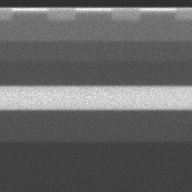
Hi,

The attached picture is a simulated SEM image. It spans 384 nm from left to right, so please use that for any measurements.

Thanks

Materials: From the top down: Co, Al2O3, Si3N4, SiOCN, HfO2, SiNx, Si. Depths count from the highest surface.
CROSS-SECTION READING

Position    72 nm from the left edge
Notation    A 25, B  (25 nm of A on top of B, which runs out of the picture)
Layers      Al2O3 66, Si3N4 40, SiOCN 50, HfO2 48, SiNx 64, Si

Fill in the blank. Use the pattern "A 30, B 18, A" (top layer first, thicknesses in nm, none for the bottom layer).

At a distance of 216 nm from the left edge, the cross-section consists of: Al2O3 66, Si3N4 40, SiOCN 50, HfO2 48, SiNx 64, Si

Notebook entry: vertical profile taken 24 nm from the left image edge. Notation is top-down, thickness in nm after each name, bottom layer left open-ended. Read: Al2O3 66, Si3N4 40, SiOCN 50, HfO2 48, SiNx 64, Si